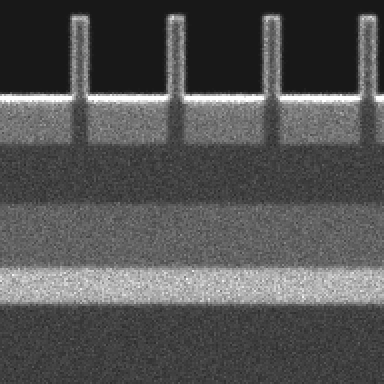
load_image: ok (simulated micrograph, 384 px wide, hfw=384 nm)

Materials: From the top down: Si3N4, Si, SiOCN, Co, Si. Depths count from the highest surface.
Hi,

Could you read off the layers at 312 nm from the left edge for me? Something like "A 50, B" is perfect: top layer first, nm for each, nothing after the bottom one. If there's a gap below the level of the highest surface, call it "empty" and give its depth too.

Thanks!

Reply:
empty 80, Si3N4 48, Si 60, SiOCN 64, Co 36, Si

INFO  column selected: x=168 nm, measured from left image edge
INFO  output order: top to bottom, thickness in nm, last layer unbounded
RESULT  Si 188, SiOCN 64, Co 36, Si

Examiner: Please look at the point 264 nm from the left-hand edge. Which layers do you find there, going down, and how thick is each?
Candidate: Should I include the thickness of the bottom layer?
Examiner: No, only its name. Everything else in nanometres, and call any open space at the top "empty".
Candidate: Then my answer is Si 188, SiOCN 64, Co 36, Si